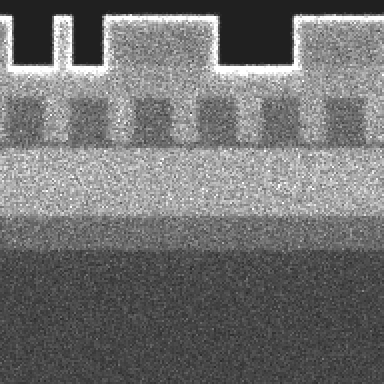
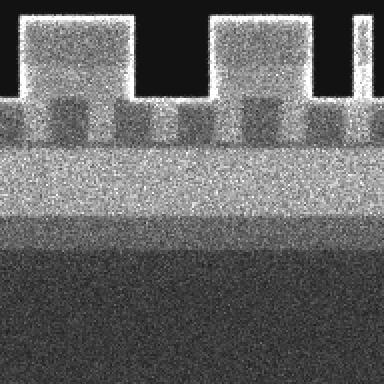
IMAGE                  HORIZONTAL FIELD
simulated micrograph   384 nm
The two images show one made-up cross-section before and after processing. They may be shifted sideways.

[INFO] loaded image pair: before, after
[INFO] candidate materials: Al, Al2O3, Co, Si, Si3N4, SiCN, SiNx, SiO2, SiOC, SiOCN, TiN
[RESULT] removed SiO2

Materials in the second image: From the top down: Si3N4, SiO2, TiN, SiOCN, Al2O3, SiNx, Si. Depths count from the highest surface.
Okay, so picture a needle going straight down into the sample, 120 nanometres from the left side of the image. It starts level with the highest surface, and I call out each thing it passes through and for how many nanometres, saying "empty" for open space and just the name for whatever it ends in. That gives Si3N4 50, SiO2 32, SiOCN 50, Al2O3 68, SiNx 34, Si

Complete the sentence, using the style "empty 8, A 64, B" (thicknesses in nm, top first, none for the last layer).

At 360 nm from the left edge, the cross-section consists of Si3N4 50, SiO2 32, TiN 44, SiOCN 6, Al2O3 68, SiNx 34, Si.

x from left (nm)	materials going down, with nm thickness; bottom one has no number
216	Si3N4 50, SiO2 32, TiN 44, SiOCN 6, Al2O3 68, SiNx 34, Si